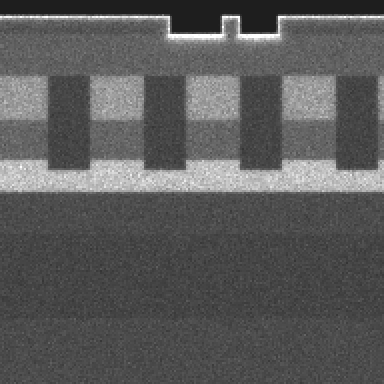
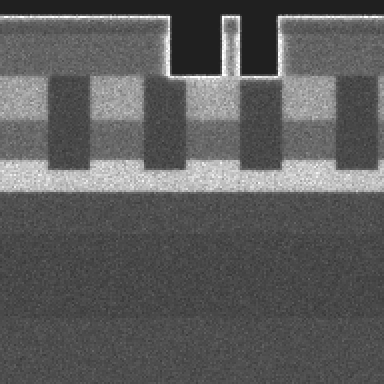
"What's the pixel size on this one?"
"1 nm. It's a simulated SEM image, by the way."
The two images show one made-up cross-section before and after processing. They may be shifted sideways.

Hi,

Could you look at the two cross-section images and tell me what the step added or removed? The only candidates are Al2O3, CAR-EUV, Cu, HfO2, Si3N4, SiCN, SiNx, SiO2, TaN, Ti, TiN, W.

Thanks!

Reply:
removed SiO2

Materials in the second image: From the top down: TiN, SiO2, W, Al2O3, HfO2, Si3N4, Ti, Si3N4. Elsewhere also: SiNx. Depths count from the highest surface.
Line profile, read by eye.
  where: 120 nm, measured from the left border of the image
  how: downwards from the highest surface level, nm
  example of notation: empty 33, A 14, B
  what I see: TiN 18, SiO2 42, W 44, Al2O3 40, HfO2 32, Si3N4 42, Ti 84, Si3N4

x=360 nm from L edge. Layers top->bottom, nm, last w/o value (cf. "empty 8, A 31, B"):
TiN 18, SiO2 42, SiNx 94, HfO2 22, Si3N4 42, Ti 84, Si3N4